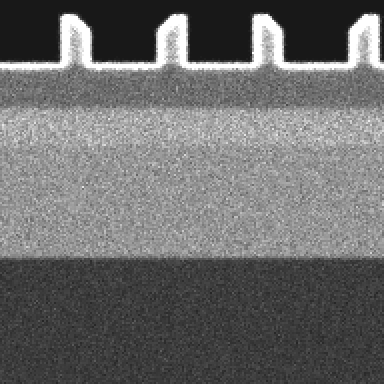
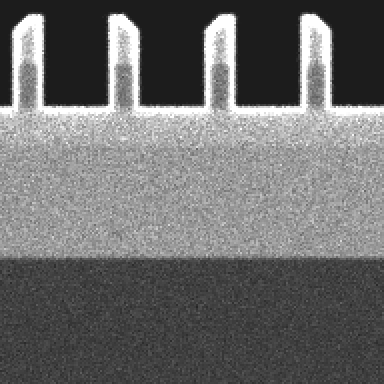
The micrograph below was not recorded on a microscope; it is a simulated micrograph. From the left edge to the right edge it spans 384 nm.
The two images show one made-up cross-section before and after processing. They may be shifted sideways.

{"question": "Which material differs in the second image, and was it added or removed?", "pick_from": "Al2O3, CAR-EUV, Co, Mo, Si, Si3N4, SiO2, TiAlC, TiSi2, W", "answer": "Si3N4, removed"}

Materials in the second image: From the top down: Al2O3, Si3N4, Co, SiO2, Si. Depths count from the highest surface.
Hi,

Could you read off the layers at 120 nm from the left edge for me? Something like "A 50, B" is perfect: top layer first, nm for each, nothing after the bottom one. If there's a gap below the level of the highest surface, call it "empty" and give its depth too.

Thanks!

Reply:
Al2O3 48, Si3N4 44, Co 38, SiO2 112, Si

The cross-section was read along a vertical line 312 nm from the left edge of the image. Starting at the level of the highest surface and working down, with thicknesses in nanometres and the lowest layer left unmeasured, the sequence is Al2O3 48, Si3N4 44, Co 38, SiO2 112, Si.